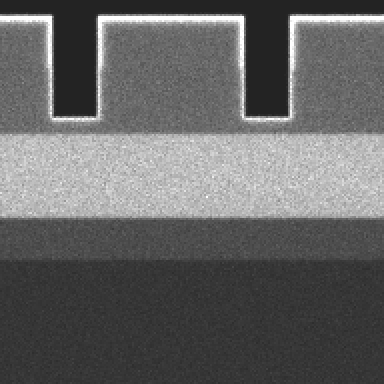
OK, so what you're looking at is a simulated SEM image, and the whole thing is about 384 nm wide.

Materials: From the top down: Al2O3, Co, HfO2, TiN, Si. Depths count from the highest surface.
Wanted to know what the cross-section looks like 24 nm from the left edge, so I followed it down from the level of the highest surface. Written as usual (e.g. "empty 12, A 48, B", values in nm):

Al2O3 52, Co 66, HfO2 84, TiN 42, Si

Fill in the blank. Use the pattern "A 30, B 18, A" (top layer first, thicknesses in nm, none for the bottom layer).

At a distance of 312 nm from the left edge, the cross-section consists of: Al2O3 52, Co 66, HfO2 84, TiN 42, Si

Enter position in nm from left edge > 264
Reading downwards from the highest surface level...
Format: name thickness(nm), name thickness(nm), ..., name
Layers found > empty 102, Co 16, HfO2 84, TiN 42, Si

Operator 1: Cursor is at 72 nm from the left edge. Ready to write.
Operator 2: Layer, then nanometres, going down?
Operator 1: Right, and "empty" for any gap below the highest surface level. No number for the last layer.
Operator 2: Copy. empty 102, Co 16, HfO2 84, TiN 42, Si